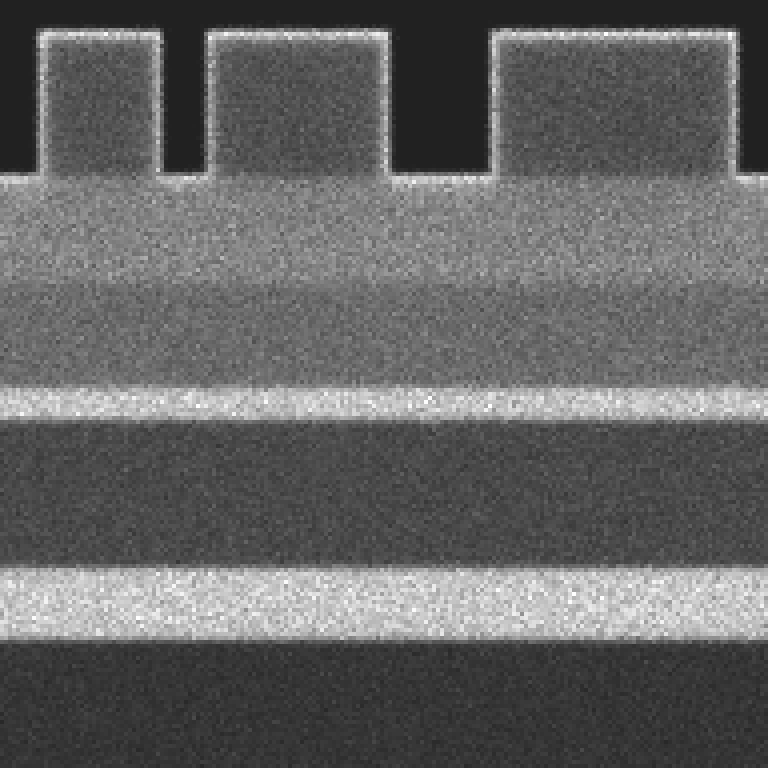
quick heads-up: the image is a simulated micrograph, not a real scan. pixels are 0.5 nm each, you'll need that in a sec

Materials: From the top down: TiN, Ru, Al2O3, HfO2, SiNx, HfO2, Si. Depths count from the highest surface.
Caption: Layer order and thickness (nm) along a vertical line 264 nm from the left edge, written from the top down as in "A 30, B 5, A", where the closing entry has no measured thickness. TiN 72, Ru 54, Al2O3 52, HfO2 16, SiNx 74, HfO2 36, Si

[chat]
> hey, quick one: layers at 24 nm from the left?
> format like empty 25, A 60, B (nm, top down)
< TiN 72, Ru 54, Al2O3 52, HfO2 16, SiNx 74, HfO2 36, Si